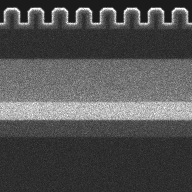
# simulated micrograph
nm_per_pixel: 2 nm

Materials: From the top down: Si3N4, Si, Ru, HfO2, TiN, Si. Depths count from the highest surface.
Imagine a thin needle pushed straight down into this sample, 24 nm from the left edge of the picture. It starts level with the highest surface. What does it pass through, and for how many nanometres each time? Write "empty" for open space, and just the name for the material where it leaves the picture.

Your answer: Si3N4 12, Si 90, Ru 86, HfO2 36, TiN 34, Si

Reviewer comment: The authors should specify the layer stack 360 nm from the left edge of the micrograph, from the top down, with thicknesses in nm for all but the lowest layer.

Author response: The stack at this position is Si3N4 12, Si 90, Ru 86, HfO2 36, TiN 34, Si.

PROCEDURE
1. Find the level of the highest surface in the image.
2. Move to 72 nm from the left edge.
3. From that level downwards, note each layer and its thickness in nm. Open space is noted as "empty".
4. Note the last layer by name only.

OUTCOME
Si3N4 12, Si 90, Ru 86, HfO2 36, TiN 34, Si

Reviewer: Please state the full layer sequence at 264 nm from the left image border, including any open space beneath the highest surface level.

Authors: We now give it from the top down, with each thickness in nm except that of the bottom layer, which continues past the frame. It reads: Si3N4 12, Si 90, Ru 86, HfO2 36, TiN 34, Si